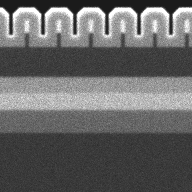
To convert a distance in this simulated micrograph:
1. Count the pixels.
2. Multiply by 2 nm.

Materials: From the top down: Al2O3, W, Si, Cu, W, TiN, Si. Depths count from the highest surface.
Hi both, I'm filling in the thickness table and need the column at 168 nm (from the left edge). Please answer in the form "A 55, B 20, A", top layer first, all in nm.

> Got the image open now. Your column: Al2O3 78, Si 60, Cu 32, W 34, TiN 46, Si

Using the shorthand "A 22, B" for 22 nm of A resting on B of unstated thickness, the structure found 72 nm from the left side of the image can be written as empty 4, Al2O3 74, Si 60, Cu 32, W 34, TiN 46, Si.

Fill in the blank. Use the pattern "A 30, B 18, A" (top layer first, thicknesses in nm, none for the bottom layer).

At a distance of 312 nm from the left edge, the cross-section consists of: Al2O3 24, W 26, Si 88, Cu 32, W 34, TiN 46, Si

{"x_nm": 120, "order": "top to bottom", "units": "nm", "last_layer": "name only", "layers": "Al2O3 24, W 26, Si 88, Cu 32, W 34, TiN 46, Si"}